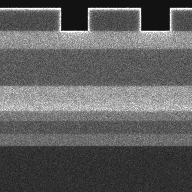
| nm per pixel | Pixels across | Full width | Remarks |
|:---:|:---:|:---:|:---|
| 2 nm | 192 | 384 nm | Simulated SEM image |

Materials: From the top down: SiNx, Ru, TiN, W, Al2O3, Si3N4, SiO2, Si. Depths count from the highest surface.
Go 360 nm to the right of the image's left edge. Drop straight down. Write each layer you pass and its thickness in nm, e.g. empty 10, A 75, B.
SiNx 46, Ru 36, TiN 74, W 50, Al2O3 20, Si3N4 26, SiO2 24, Si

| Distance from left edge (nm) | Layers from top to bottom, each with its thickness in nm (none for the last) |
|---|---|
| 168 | empty 46, Ru 36, TiN 74, W 50, Al2O3 20, Si3N4 26, SiO2 24, Si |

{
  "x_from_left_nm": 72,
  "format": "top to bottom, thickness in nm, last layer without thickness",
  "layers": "SiNx 46, Ru 36, TiN 74, W 50, Al2O3 20, Si3N4 26, SiO2 24, Si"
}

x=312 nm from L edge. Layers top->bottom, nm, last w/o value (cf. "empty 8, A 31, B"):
empty 46, Ru 36, TiN 74, W 50, Al2O3 20, Si3N4 26, SiO2 24, Si